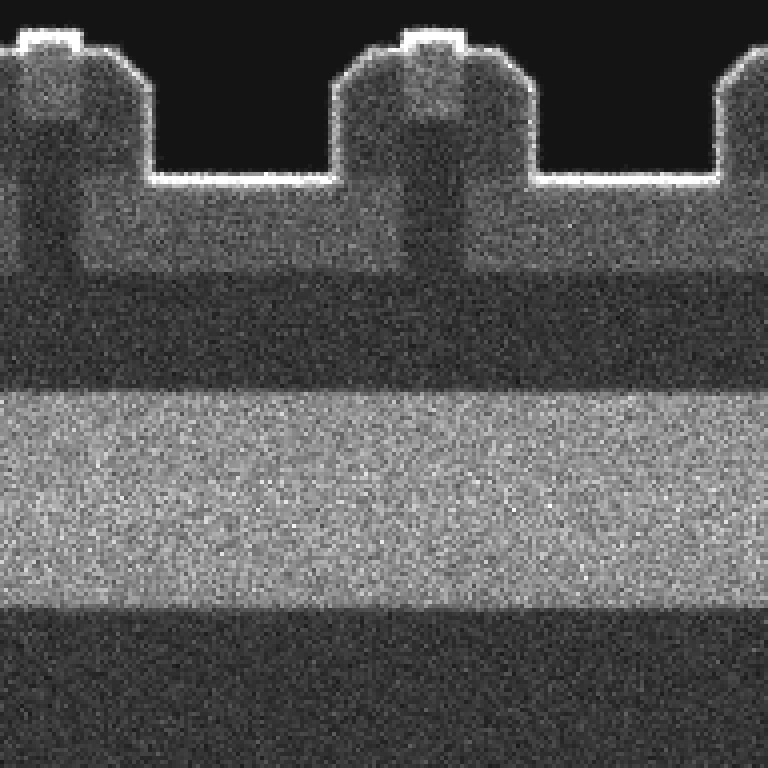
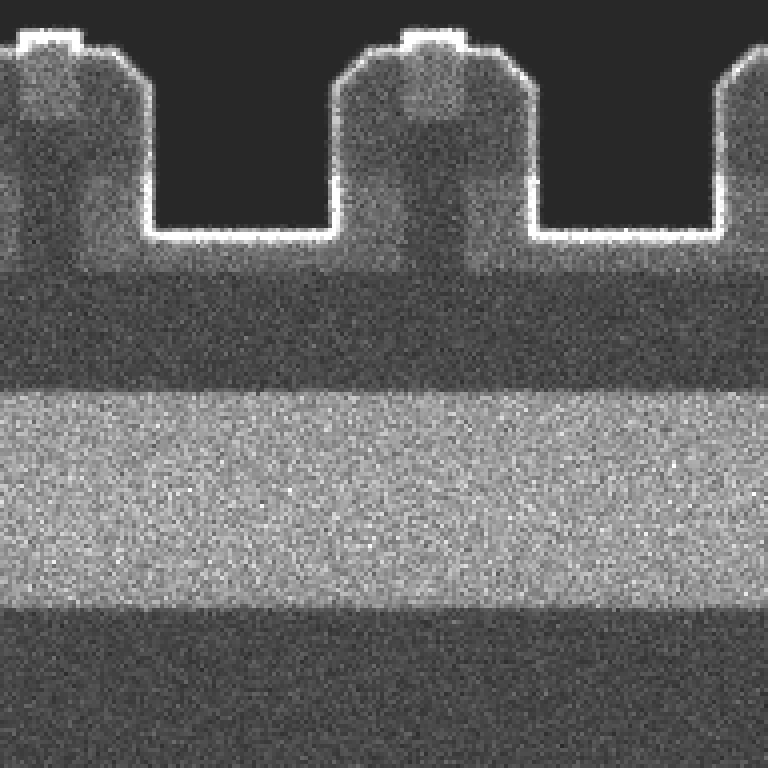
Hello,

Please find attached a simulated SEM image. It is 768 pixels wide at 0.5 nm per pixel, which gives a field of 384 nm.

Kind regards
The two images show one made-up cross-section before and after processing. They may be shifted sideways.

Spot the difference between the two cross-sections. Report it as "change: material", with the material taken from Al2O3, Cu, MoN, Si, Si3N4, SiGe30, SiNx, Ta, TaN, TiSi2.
removed: SiNx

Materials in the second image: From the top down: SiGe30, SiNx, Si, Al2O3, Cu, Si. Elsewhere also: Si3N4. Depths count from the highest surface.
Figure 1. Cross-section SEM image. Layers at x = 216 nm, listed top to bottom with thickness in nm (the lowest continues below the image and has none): Si3N4 44, Si 136, Al2O3 40, Cu 68, Si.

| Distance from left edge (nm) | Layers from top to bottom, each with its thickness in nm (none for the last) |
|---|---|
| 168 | empty 24, SiGe30 48, SiNx 48, Si 60, Al2O3 40, Cu 68, Si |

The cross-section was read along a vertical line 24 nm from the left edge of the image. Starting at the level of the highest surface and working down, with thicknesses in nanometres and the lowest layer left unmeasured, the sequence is Si3N4 44, Si 136, Al2O3 40, Cu 68, Si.